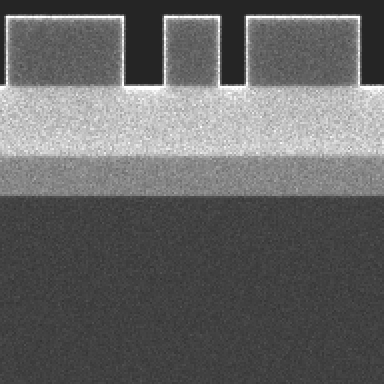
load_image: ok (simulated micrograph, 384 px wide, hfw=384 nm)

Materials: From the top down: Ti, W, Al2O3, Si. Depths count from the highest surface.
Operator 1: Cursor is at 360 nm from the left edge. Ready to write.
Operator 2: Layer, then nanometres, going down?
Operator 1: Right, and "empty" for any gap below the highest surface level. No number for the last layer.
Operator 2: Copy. empty 70, W 70, Al2O3 40, Si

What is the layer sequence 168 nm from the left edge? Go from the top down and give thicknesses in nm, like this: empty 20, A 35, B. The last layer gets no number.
Ti 70, W 70, Al2O3 40, Si